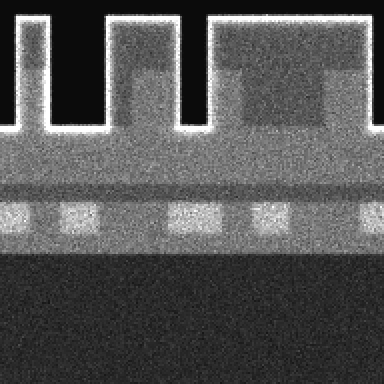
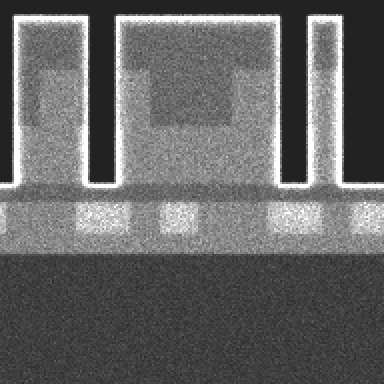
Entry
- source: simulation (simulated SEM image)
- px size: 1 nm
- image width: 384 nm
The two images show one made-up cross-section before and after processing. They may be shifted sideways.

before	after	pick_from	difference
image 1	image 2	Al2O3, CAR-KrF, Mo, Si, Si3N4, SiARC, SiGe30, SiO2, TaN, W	SiO2 removed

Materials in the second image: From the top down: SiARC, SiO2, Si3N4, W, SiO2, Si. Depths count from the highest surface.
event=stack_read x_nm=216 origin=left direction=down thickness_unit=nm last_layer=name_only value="SiARC 110, SiO2 58, Si3N4 18, SiO2 52, Si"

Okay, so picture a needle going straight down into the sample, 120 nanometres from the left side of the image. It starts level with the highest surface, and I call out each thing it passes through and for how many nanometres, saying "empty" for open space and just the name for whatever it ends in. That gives SiARC 110, SiO2 58, Si3N4 18, W 32, SiO2 20, Si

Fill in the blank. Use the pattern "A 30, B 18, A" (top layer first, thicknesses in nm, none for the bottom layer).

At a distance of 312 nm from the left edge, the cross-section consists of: SiARC 110, SiO2 58, Si3N4 18, W 32, SiO2 20, Si